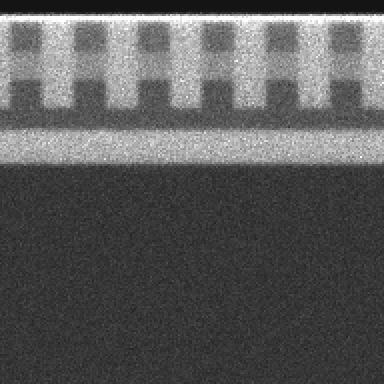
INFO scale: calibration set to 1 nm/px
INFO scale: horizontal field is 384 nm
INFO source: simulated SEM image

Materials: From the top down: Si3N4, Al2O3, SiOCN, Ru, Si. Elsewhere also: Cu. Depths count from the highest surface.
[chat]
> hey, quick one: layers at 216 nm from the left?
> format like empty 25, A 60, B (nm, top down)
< Si3N4 36, Al2O3 28, SiOCN 50, Ru 34, Si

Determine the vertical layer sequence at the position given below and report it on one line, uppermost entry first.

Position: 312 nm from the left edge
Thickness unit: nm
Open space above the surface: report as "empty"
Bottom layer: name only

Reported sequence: Cu 92, SiOCN 22, Ru 34, Si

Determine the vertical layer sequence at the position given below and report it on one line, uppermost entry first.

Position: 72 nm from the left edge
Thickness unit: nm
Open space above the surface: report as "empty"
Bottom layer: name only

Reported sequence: Cu 92, SiOCN 22, Ru 34, Si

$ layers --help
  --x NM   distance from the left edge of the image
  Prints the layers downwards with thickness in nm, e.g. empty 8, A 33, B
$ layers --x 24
Si3N4 36, Al2O3 28, SiOCN 50, Ru 34, Si